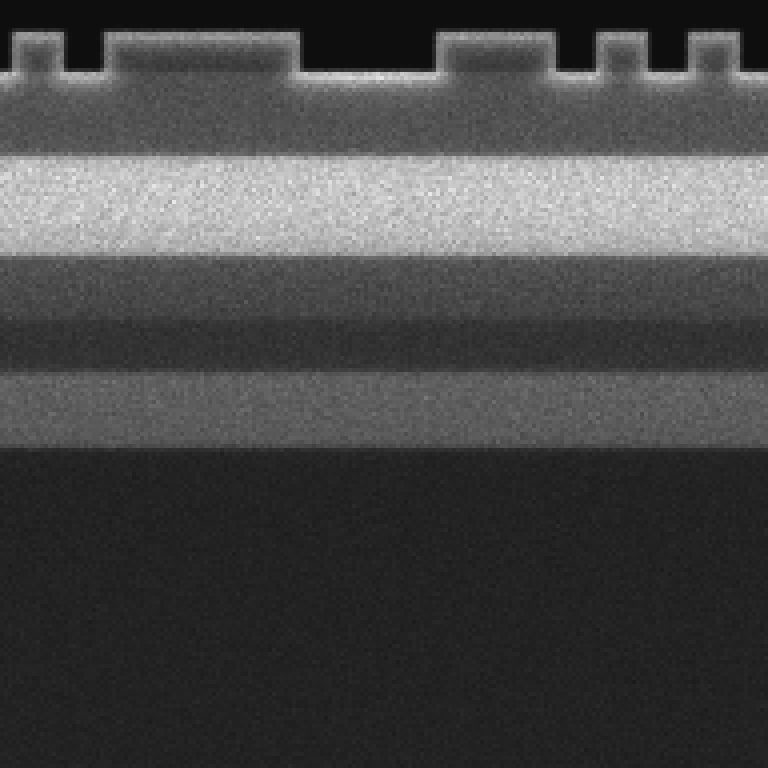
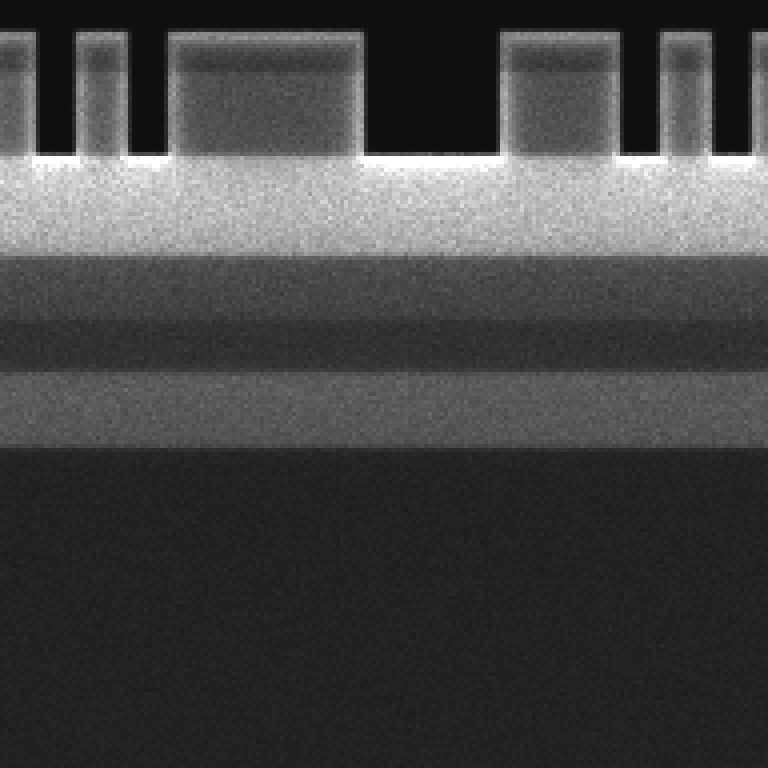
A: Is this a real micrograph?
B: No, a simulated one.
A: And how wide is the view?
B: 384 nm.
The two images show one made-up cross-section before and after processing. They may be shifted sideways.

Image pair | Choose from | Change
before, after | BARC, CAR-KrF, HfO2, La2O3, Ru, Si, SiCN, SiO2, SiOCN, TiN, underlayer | SiO2 (removed)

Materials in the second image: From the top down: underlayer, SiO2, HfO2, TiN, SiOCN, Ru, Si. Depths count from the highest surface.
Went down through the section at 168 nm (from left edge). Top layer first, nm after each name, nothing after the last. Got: underlayer 20, SiO2 42, HfO2 50, TiN 32, SiOCN 26, Ru 38, Si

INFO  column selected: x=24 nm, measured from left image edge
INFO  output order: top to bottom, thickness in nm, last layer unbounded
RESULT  empty 62, HfO2 50, TiN 32, SiOCN 26, Ru 38, Si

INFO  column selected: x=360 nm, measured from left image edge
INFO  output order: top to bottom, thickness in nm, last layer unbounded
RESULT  empty 62, HfO2 50, TiN 32, SiOCN 26, Ru 38, Si